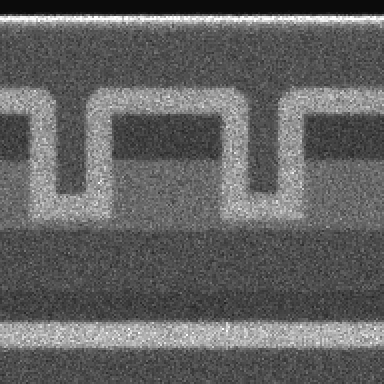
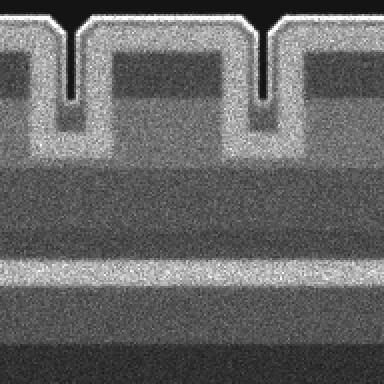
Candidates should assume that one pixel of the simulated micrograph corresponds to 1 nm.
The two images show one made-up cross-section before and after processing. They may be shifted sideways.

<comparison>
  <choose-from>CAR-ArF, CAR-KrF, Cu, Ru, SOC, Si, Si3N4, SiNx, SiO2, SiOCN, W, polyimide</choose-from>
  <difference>SOC removed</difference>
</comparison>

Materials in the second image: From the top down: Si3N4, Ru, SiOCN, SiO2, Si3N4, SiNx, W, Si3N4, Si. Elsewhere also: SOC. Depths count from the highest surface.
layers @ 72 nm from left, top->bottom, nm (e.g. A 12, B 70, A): empty 84, SOC 22, Si3N4 10, Ru 26, SiO2 10, Si3N4 62, SiNx 30, W 26, Si3N4 58, Si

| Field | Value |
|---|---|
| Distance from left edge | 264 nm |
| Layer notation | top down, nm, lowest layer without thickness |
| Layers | empty 84, SOC 22, Si3N4 10, Ru 26, SiO2 10, Si3N4 62, SiNx 30, W 26, Si3N4 58, Si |